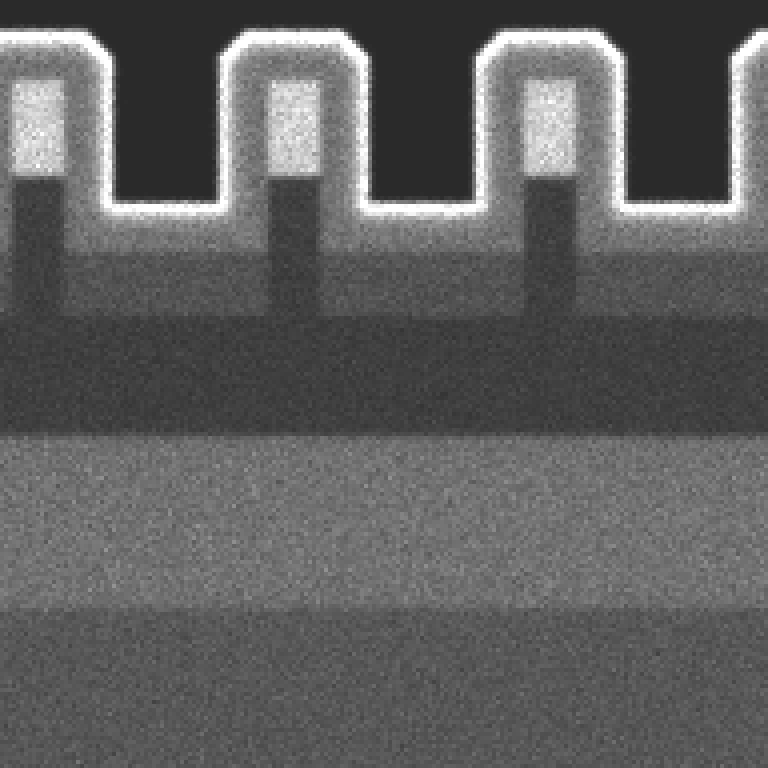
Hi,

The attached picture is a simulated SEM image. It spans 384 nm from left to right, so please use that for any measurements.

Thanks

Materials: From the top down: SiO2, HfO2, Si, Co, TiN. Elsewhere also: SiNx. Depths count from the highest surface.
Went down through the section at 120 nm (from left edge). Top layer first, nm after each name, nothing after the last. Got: empty 2, SiO2 108, SiNx 32, Si 60, Co 86, TiN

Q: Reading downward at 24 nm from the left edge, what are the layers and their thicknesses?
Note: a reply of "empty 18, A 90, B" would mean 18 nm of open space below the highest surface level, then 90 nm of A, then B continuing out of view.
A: SiO2 24, HfO2 48, Si 130, Co 86, TiN